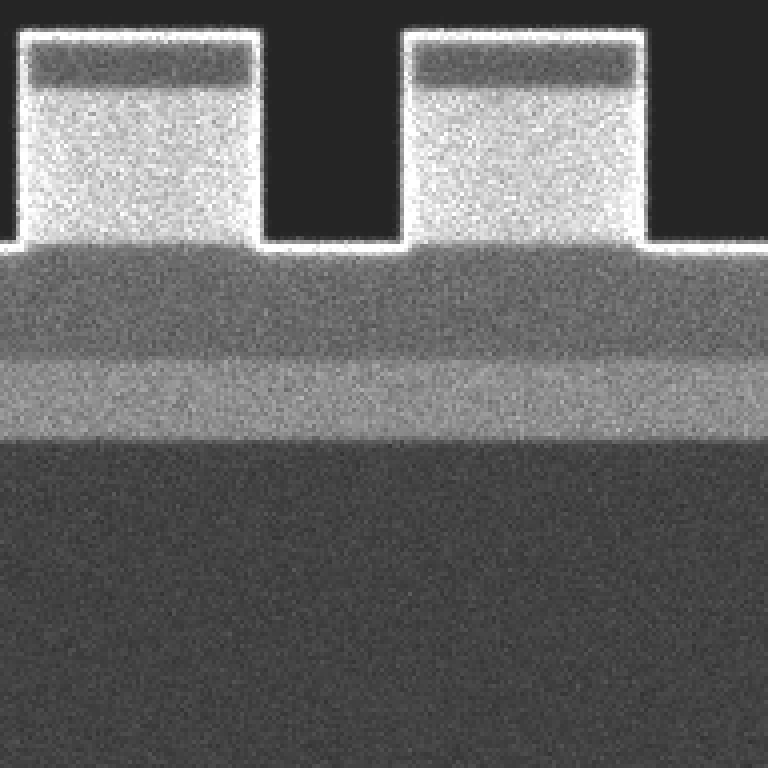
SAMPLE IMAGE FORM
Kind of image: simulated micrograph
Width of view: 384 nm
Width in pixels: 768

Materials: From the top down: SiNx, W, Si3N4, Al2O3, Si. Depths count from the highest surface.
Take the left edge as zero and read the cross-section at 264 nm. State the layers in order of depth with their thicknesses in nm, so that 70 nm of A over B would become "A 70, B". SiNx 28, W 78, Si3N4 58, Al2O3 40, Si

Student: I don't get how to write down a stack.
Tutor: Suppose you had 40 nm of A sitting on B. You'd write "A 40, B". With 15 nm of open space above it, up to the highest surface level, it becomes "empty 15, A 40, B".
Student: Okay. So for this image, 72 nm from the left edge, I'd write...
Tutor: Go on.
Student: SiNx 28, W 78, Si3N4 58, Al2O3 40, Si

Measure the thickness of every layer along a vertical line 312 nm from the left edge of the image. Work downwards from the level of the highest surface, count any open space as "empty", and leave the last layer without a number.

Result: SiNx 28, W 78, Si3N4 58, Al2O3 40, Si